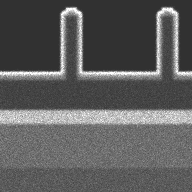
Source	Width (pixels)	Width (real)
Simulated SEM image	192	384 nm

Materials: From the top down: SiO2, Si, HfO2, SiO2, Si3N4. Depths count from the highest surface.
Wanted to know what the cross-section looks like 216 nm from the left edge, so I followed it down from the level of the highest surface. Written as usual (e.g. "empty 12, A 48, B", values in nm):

empty 128, SiO2 16, Si 60, HfO2 28, SiO2 88, Si3N4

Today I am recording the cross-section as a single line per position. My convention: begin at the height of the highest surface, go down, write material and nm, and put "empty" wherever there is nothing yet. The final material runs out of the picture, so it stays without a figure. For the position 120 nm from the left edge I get empty 128, SiO2 16, Si 60, HfO2 28, SiO2 88, Si3N4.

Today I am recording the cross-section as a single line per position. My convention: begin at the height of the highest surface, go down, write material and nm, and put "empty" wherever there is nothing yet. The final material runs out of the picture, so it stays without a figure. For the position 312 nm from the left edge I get empty 128, SiO2 16, Si 60, HfO2 28, SiO2 88, Si3N4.